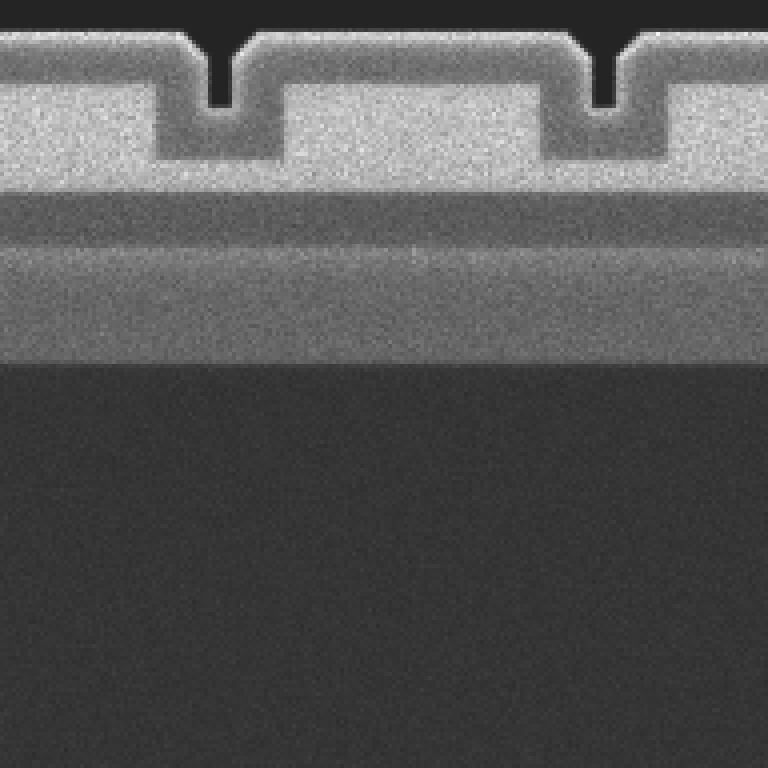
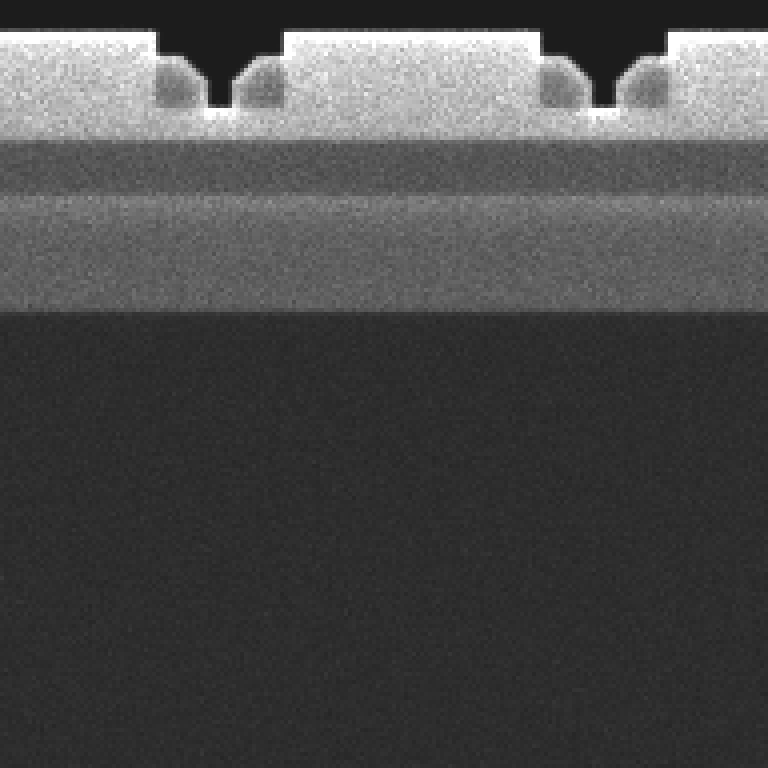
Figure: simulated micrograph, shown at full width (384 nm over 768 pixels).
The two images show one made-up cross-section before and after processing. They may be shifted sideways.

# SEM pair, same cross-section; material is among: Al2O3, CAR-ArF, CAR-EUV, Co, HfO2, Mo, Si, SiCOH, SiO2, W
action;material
removed;Al2O3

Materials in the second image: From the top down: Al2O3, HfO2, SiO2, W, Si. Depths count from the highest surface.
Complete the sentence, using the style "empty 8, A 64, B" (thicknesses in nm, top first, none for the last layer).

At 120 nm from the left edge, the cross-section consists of empty 20, Al2O3 18, HfO2 16, SiO2 28, W 58, Si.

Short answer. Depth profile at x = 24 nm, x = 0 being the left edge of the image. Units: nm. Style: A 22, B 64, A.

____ HfO2 54, SiO2 28, W 58, Si